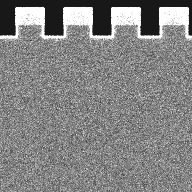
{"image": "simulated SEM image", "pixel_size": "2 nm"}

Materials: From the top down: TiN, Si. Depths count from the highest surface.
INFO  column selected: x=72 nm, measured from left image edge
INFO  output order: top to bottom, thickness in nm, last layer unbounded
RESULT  TiN 34, Si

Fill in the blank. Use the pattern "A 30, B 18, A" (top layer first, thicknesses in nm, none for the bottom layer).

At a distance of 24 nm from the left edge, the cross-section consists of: empty 56, Si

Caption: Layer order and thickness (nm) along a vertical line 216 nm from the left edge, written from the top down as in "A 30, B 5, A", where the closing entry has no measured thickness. empty 56, Si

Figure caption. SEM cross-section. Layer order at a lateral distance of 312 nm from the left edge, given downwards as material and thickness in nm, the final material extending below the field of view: empty 56, Si